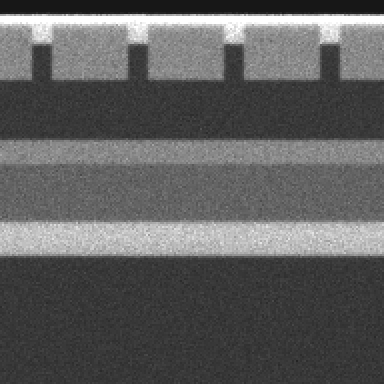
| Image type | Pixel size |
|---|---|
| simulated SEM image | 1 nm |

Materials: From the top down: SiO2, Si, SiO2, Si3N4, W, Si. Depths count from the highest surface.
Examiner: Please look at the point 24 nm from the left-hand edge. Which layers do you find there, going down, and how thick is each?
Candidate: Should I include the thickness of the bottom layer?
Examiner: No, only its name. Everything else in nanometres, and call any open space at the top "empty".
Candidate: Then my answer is SiO2 64, Si 60, SiO2 24, Si3N4 58, W 34, Si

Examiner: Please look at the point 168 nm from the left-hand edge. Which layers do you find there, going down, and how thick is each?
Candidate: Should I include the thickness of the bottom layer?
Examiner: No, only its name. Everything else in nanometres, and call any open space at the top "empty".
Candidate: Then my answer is SiO2 64, Si 60, SiO2 24, Si3N4 58, W 34, Si